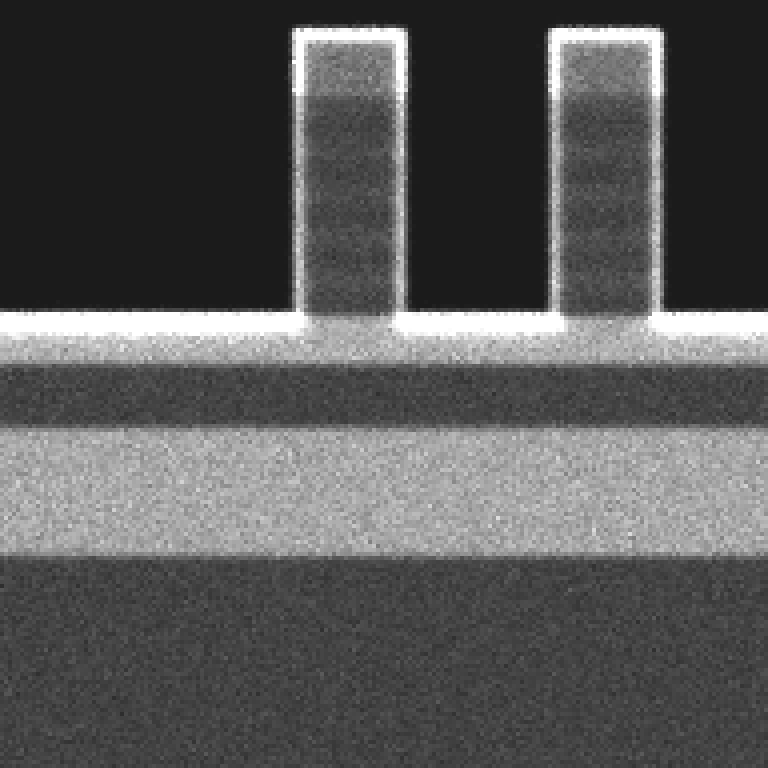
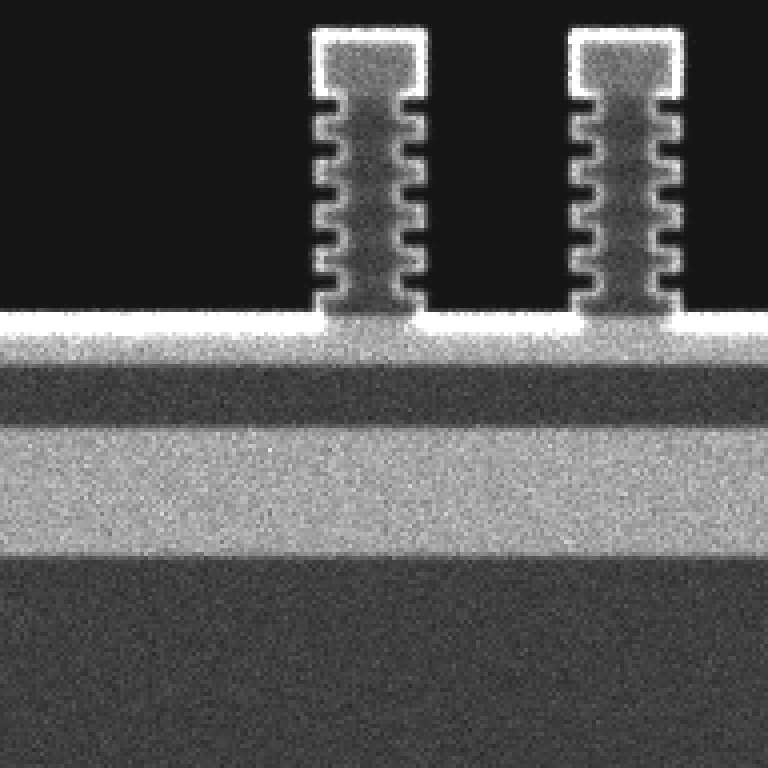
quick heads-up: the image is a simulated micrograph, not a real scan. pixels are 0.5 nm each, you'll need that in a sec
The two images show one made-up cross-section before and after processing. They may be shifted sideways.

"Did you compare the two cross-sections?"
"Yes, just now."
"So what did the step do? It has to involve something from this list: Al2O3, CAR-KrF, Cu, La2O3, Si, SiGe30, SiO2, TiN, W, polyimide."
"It removed SiGe30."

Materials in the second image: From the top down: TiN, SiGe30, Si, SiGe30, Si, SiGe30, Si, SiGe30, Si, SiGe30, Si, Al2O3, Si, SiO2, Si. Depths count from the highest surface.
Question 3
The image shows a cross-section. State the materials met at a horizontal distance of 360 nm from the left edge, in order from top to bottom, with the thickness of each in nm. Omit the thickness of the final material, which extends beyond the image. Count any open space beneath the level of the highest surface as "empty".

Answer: empty 142, Al2O3 24, Si 32, SiO2 64, Si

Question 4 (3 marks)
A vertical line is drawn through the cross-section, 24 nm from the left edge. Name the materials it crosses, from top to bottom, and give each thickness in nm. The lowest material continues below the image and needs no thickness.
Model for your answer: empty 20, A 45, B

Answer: empty 142, Al2O3 24, Si 32, SiO2 64, Si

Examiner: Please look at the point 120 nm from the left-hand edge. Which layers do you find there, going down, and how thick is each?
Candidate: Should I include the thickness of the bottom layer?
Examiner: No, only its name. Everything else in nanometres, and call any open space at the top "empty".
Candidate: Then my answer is empty 142, Al2O3 24, Si 32, SiO2 64, Si